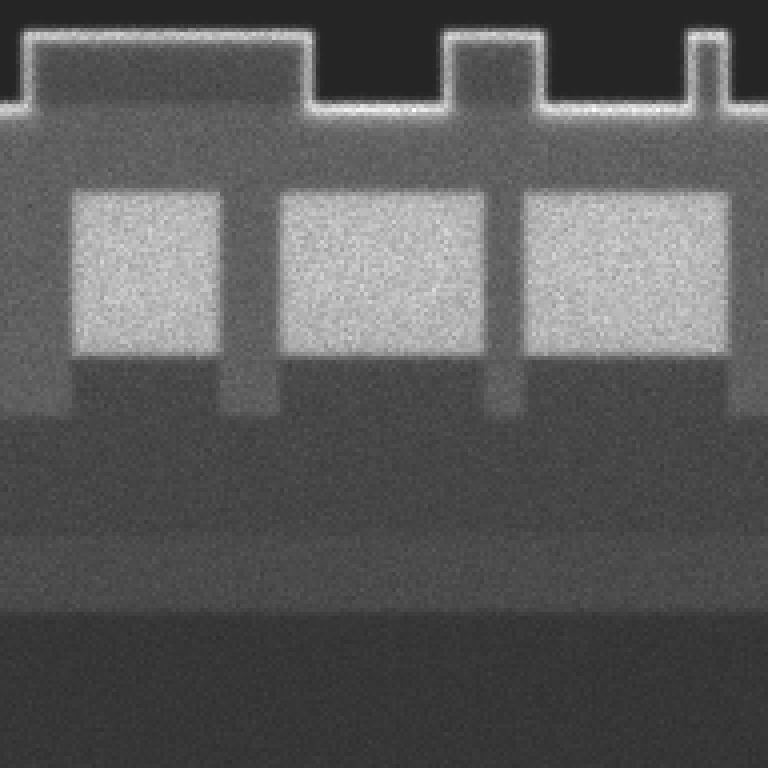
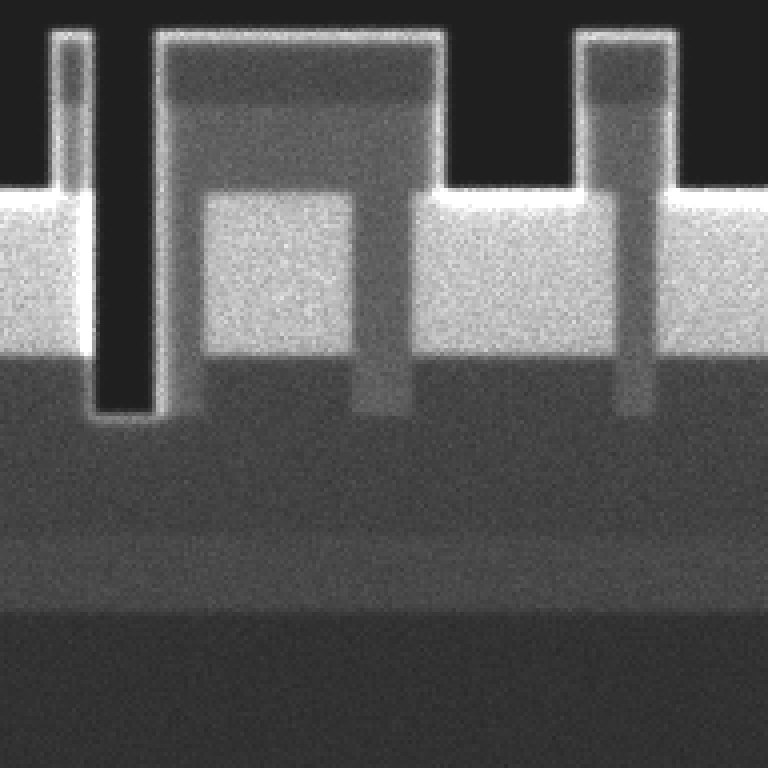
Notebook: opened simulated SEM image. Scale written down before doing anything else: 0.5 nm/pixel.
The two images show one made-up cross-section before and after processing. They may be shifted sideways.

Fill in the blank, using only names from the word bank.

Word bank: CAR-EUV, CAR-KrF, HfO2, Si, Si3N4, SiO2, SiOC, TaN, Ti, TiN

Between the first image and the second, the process removed SiO2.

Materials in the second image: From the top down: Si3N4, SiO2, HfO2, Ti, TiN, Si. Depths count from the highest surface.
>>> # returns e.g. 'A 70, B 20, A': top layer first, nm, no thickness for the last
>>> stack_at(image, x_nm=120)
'Si3N4 36, SiO2 44, HfO2 82, Ti 90, TiN 38, Si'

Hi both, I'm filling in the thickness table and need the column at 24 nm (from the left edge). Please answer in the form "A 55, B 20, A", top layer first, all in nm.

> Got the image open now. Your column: empty 80, HfO2 82, Ti 90, TiN 38, Si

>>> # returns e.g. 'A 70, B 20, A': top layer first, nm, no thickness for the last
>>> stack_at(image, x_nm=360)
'empty 80, HfO2 82, Ti 90, TiN 38, Si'